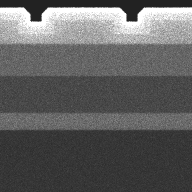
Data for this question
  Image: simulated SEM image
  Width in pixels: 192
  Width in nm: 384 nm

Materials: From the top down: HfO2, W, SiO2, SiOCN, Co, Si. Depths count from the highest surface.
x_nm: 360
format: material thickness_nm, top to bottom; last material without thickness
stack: HfO2 24, W 48, SiO2 64, SiOCN 74, Co 34, Si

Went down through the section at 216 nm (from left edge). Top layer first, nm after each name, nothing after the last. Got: HfO2 24, W 48, SiO2 64, SiOCN 74, Co 34, Si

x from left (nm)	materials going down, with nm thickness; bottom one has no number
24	HfO2 24, W 48, SiO2 64, SiOCN 74, Co 34, Si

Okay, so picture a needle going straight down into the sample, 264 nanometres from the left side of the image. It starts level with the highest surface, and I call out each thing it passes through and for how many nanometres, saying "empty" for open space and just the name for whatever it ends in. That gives empty 28, HfO2 24, W 20, SiO2 64, SiOCN 74, Co 34, Si